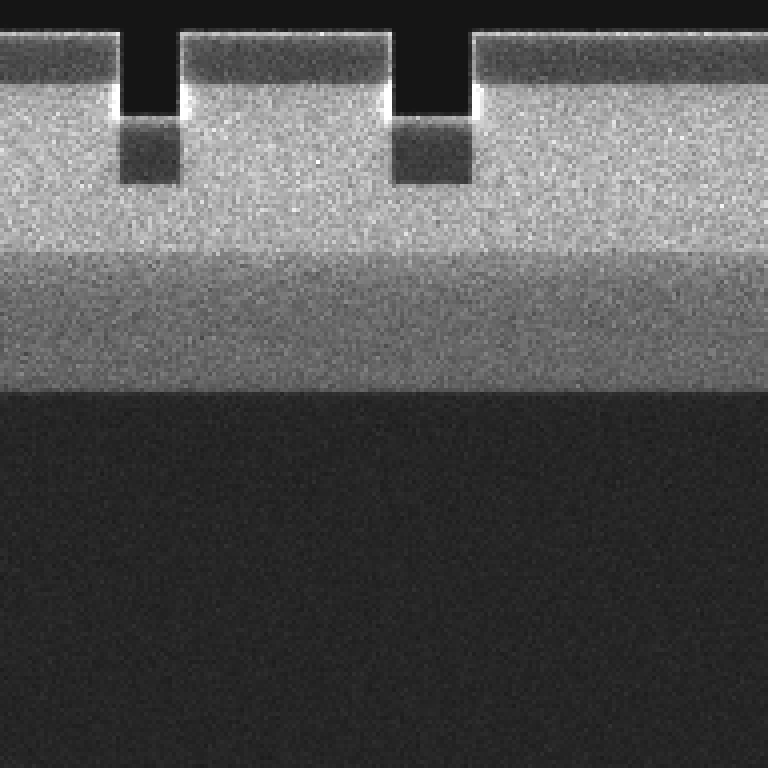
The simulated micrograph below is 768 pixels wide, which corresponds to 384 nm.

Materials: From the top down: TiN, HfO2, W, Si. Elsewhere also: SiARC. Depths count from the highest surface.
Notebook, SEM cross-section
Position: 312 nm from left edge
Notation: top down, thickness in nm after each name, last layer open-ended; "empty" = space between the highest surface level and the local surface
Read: TiN 26, HfO2 84, W 70, Si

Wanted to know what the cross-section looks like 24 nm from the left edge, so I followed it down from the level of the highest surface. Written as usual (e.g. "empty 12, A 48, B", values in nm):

TiN 26, HfO2 84, W 70, Si